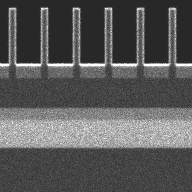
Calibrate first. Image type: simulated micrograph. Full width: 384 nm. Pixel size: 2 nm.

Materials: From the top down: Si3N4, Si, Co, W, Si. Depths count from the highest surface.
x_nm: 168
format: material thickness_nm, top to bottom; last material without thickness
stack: empty 112, Si3N4 28, Si 60, Co 24, W 56, Si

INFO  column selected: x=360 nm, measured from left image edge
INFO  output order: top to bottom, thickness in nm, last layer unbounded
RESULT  empty 112, Si3N4 28, Si 60, Co 24, W 56, Si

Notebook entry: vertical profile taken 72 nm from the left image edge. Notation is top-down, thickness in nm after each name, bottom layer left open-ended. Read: empty 112, Si3N4 28, Si 60, Co 24, W 56, Si